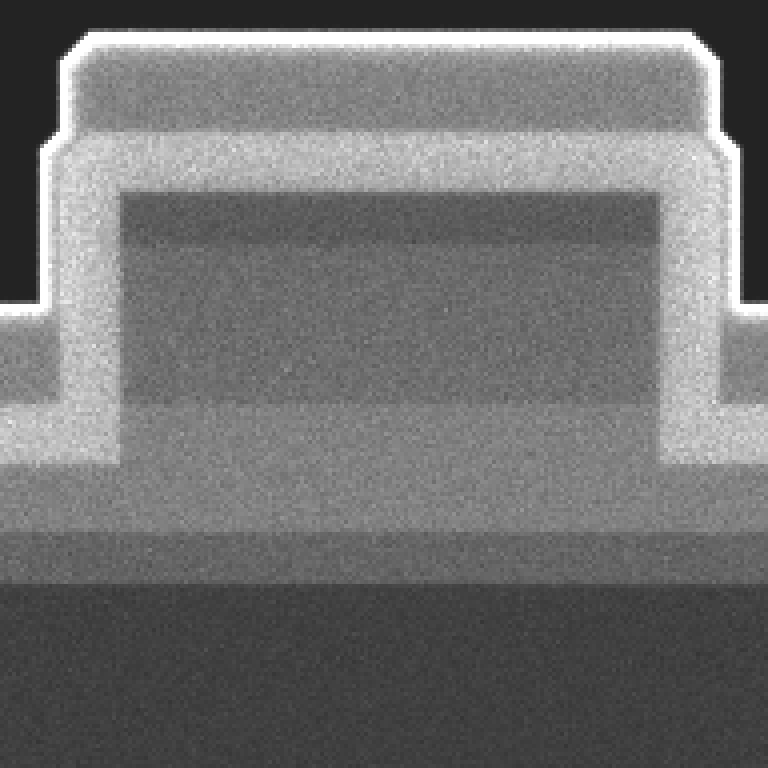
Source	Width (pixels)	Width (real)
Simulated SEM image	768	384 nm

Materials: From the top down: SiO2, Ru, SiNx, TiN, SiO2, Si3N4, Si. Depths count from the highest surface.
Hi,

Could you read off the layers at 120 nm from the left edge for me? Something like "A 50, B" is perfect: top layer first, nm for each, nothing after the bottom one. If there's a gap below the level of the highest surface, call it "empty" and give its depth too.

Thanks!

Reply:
SiO2 50, Ru 30, SiNx 26, TiN 80, SiO2 64, Si3N4 26, Si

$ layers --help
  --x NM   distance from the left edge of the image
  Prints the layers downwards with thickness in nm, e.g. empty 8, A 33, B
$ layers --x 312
SiO2 50, Ru 30, SiNx 26, TiN 80, SiO2 64, Si3N4 26, Si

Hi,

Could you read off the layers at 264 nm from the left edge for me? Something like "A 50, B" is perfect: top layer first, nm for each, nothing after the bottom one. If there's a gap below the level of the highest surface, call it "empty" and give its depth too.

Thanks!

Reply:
SiO2 50, Ru 30, SiNx 26, TiN 80, SiO2 64, Si3N4 26, Si